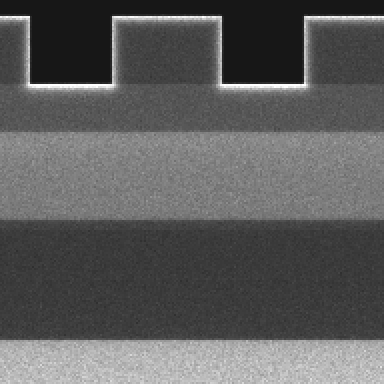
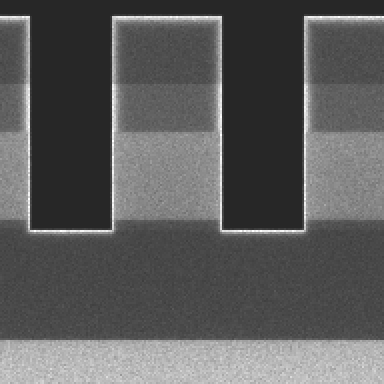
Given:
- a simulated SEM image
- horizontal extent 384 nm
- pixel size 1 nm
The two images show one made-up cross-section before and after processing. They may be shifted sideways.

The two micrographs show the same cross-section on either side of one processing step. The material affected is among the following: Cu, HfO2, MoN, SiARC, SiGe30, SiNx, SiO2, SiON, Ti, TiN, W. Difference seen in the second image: SiO2 and TiN and W removed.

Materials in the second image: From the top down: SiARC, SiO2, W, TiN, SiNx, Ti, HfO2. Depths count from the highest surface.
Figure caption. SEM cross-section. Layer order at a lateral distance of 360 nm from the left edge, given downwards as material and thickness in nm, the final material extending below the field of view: SiARC 68, SiO2 48, W 88, TiN 10, SiNx 50, Ti 60, HfO2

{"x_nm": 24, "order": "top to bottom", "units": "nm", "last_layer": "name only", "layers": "SiARC 68, SiO2 48, W 88, TiN 10, SiNx 50, Ti 60, HfO2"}